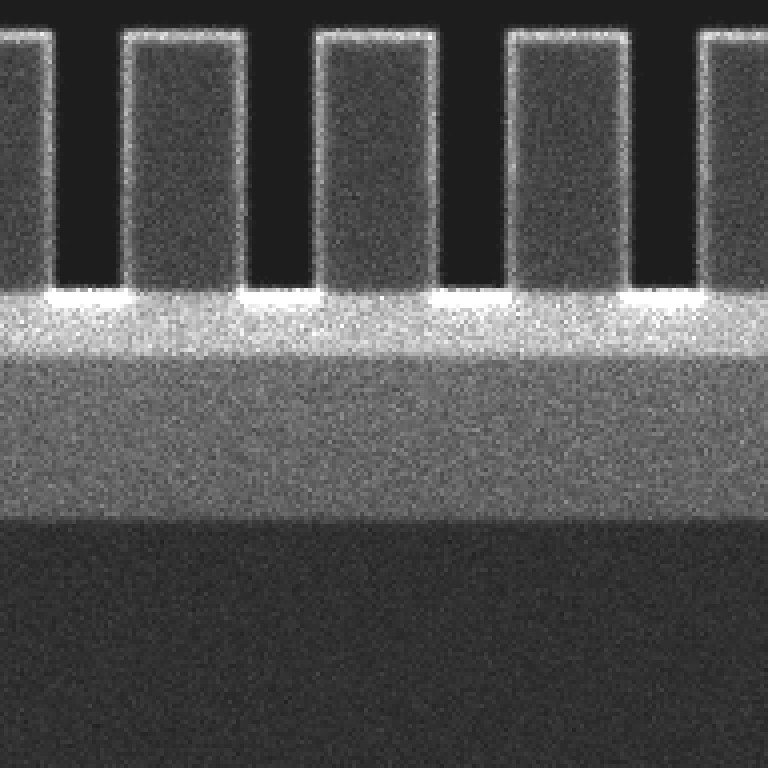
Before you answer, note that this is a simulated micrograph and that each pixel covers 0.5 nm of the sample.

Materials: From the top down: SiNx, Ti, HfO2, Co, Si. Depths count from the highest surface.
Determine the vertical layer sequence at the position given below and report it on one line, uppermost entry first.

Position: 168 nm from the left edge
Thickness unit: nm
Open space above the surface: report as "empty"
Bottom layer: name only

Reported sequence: SiNx 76, Ti 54, HfO2 32, Co 82, Si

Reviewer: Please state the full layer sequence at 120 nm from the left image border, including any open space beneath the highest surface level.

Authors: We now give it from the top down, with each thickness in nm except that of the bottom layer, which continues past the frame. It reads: SiNx 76, Ti 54, HfO2 32, Co 82, Si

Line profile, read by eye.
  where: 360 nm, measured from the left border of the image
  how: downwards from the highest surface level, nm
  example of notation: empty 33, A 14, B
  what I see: SiNx 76, Ti 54, HfO2 32, Co 82, Si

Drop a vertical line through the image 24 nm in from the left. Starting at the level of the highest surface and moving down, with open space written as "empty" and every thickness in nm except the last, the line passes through SiNx 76, Ti 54, HfO2 32, Co 82, Si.